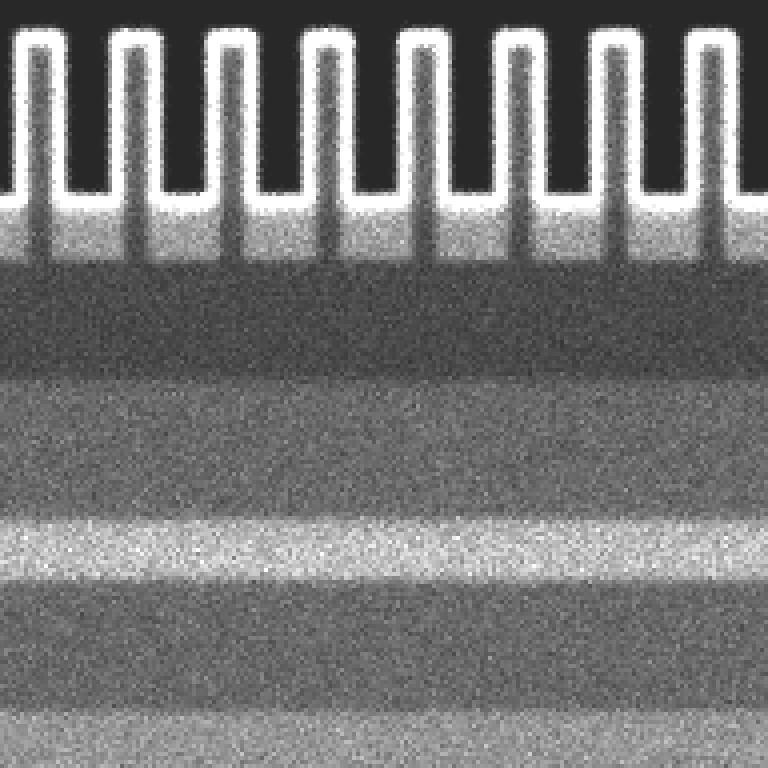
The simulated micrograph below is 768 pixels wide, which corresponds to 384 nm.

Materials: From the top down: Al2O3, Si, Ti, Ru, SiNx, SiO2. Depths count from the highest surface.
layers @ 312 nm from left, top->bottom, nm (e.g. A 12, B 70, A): Al2O3 6, Si 168, Ti 70, Ru 30, SiNx 66, SiO2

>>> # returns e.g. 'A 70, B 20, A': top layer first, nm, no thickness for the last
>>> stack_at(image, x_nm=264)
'Al2O3 6, Si 168, Ti 70, Ru 30, SiNx 66, SiO2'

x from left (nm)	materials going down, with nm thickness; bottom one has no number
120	Al2O3 6, Si 168, Ti 70, Ru 30, SiNx 66, SiO2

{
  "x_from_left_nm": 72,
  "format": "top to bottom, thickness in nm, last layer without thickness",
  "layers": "Al2O3 6, Si 168, Ti 70, Ru 30, SiNx 66, SiO2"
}